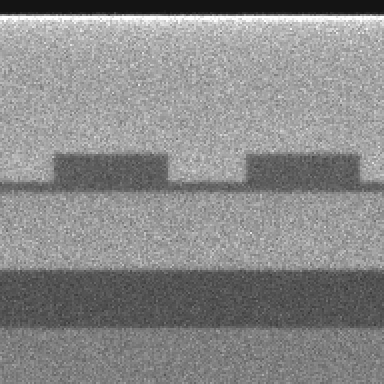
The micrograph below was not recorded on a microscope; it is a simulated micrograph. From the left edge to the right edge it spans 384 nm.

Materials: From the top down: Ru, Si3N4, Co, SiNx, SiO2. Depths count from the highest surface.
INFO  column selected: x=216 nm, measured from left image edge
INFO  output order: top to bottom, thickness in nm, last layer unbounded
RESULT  Ru 166, Si3N4 10, Co 78, SiNx 58, SiO2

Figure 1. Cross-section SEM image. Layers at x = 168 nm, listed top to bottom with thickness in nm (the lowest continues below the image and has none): Ru 166, Si3N4 10, Co 78, SiNx 58, SiO2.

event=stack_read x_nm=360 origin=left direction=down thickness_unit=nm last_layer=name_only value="Ru 166, Si3N4 10, Co 78, SiNx 58, SiO2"